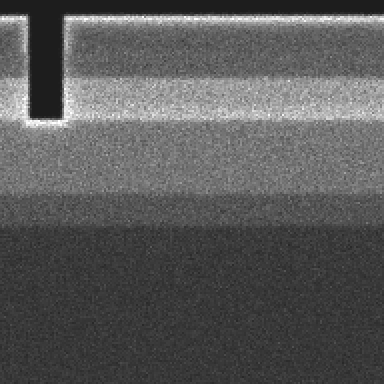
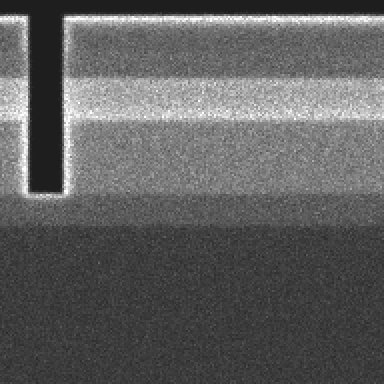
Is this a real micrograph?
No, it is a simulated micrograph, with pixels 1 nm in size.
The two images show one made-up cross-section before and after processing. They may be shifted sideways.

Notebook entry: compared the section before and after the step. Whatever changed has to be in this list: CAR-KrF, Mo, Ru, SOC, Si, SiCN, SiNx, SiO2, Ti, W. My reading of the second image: SiO2 removed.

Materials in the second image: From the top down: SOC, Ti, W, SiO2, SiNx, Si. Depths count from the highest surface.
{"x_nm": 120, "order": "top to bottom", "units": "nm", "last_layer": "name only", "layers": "SOC 36, Ti 26, W 42, SiO2 74, SiNx 32, Si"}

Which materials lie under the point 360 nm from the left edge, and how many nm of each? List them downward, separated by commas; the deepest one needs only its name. SOC 36, Ti 26, W 42, SiO2 74, SiNx 32, Si